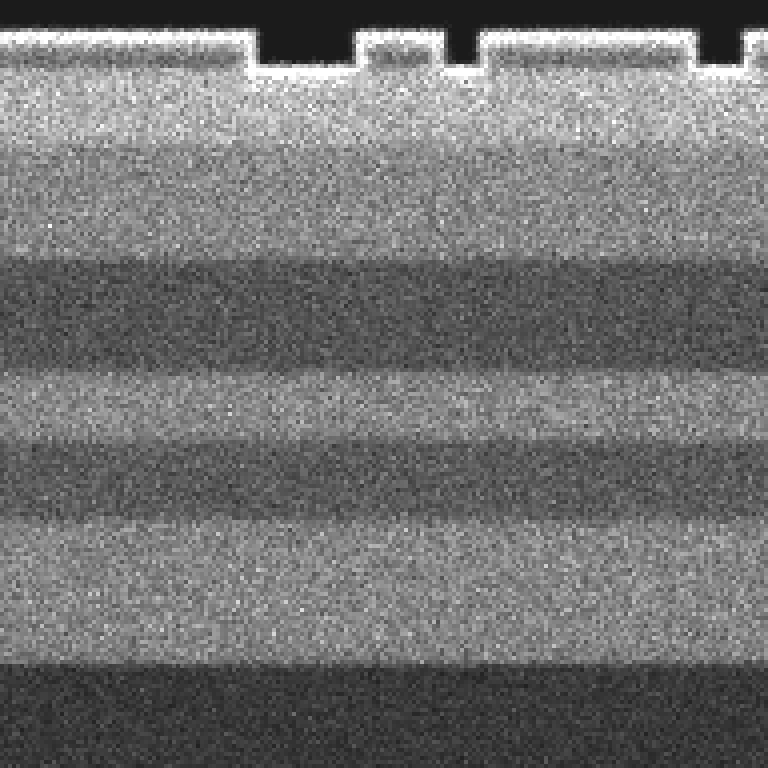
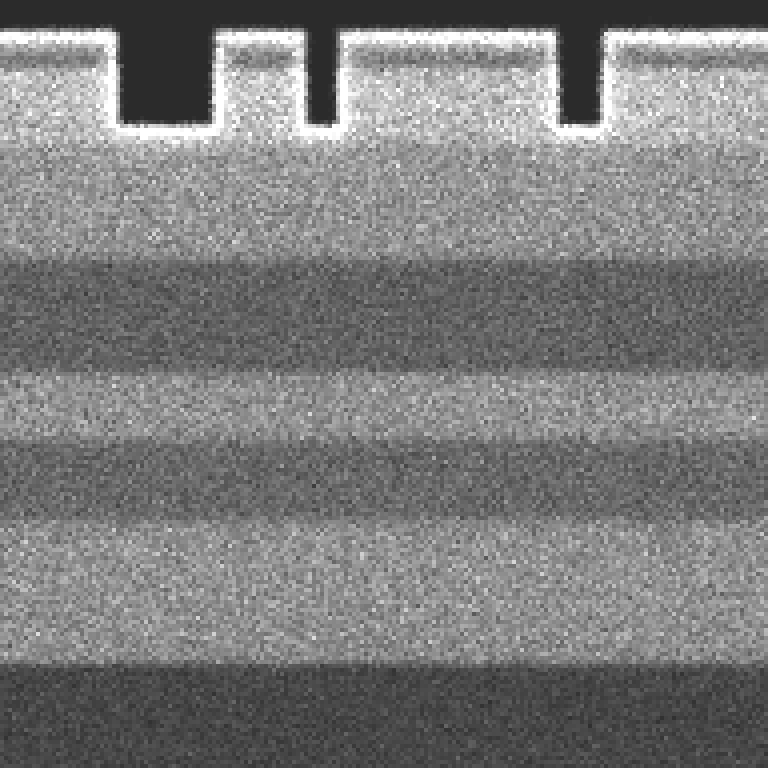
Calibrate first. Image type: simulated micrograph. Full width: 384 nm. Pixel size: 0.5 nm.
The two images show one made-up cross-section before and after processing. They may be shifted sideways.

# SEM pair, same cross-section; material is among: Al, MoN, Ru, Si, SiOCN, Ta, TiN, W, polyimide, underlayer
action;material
removed;W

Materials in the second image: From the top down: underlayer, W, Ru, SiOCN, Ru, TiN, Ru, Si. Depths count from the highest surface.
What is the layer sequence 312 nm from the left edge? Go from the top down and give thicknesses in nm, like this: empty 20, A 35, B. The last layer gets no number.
underlayer 18, W 38, Ru 58, SiOCN 56, Ru 34, TiN 40, Ru 72, Si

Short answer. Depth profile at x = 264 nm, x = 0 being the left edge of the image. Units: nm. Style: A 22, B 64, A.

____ underlayer 18, W 38, Ru 58, SiOCN 56, Ru 34, TiN 40, Ru 72, Si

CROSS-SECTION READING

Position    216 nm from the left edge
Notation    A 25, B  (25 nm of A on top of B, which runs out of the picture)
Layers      underlayer 18, W 38, Ru 58, SiOCN 56, Ru 34, TiN 40, Ru 72, Si